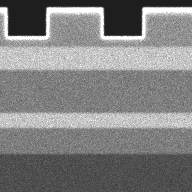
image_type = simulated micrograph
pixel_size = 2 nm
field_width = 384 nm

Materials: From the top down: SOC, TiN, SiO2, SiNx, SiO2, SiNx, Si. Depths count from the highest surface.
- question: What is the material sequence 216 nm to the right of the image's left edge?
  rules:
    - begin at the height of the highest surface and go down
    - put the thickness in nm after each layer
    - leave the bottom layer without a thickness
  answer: empty 58, TiN 20, SiO2 46, SiNx 86, SiO2 30, SiNx 52, Si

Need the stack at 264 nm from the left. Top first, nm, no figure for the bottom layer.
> empty 58, TiN 20, SiO2 46, SiNx 86, SiO2 30, SiNx 52, Si